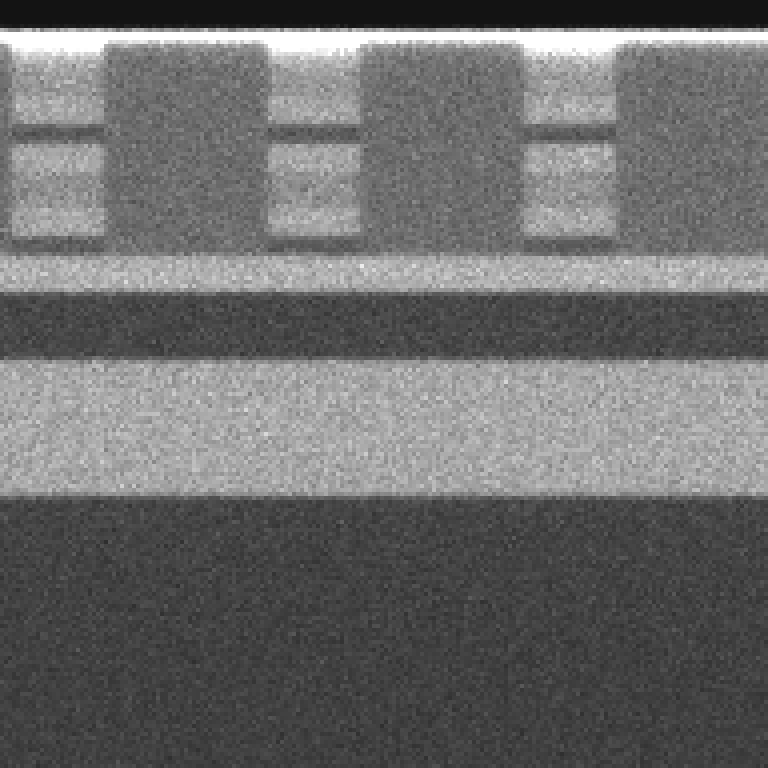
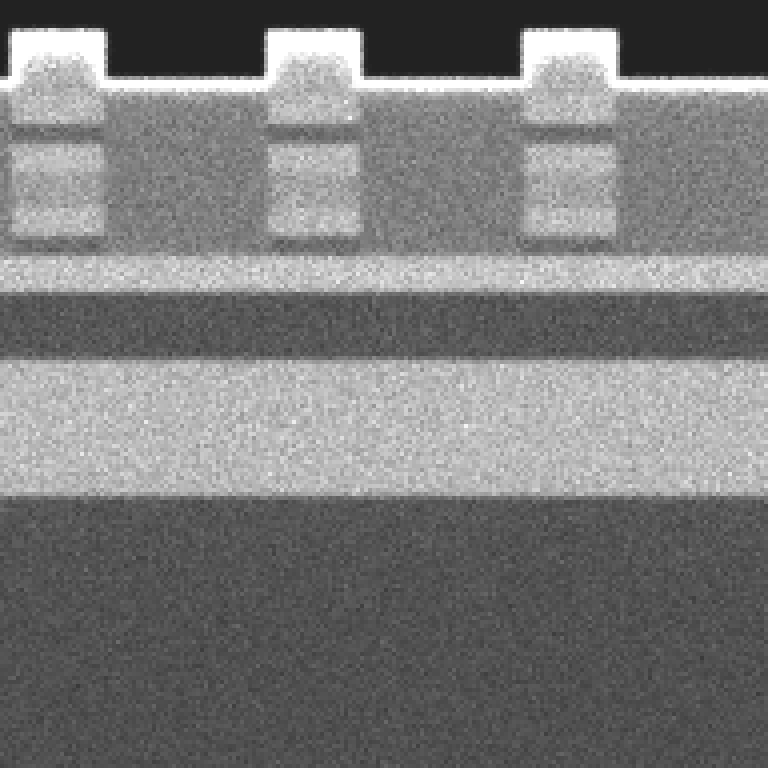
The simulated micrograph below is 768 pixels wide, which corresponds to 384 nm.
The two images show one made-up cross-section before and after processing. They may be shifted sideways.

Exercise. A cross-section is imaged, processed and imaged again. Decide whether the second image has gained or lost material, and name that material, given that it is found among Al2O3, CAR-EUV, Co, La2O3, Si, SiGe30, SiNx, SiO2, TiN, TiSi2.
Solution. removed: SiNx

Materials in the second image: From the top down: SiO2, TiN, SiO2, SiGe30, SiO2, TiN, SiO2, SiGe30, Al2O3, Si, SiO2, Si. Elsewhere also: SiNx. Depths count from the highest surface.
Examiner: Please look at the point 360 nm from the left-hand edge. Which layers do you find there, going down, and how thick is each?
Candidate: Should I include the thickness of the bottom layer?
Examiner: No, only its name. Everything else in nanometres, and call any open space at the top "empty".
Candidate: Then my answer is empty 24, SiNx 88, Al2O3 18, Si 34, SiO2 68, Si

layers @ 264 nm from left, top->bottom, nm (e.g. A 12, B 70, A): SiO2 14, TiN 18, SiO2 14, SiGe30 10, SiO2 14, TiN 18, SiO2 14, SiGe30 10, Al2O3 18, Si 34, SiO2 68, Si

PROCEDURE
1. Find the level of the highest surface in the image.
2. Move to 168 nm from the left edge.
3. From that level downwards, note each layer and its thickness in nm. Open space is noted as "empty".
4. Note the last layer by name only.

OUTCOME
SiO2 14, TiN 18, SiO2 14, SiGe30 10, SiO2 14, TiN 18, SiO2 14, SiGe30 10, Al2O3 18, Si 34, SiO2 68, Si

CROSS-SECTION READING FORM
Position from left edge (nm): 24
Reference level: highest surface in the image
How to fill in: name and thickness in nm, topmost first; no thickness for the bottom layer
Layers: SiO2 14, TiN 18, SiO2 14, SiGe30 10, SiO2 14, TiN 18, SiO2 14, SiGe30 10, Al2O3 18, Si 34, SiO2 68, Si